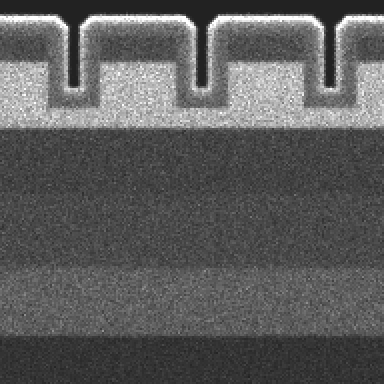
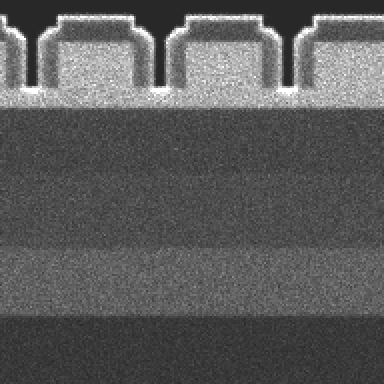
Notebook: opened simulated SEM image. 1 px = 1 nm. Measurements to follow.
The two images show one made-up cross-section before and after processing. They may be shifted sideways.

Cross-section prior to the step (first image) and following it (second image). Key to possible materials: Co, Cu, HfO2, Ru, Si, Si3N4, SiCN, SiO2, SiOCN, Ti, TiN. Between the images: SiO2 was removed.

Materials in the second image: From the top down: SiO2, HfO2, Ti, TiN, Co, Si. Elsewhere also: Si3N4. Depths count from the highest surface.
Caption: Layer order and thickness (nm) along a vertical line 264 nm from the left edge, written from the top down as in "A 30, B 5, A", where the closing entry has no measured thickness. empty 12, SiO2 60, HfO2 20, Ti 66, TiN 74, Co 68, Si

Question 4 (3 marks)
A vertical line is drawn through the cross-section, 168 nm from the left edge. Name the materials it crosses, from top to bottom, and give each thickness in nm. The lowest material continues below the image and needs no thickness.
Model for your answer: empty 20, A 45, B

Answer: empty 20, SiO2 52, HfO2 20, Ti 66, TiN 74, Co 68, Si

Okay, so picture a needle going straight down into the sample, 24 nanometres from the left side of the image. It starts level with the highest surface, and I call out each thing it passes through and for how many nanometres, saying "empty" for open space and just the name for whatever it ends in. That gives empty 22, SiO2 50, HfO2 20, Ti 66, TiN 74, Co 68, Si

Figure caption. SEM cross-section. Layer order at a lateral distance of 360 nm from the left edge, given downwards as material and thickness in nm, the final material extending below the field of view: Si3N4 26, HfO2 66, Ti 66, TiN 74, Co 68, Si